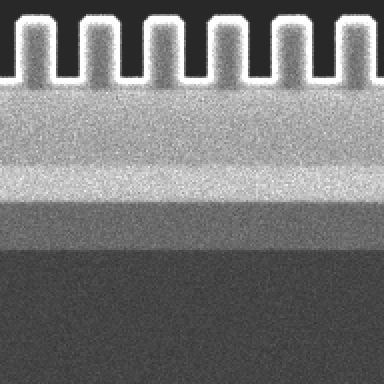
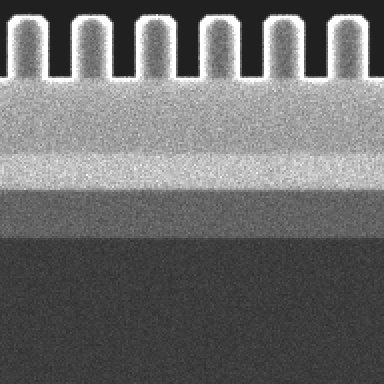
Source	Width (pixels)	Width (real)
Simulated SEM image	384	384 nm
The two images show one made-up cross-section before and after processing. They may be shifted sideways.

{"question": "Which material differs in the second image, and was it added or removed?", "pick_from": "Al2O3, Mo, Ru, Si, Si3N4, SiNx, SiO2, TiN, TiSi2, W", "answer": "SiO2, removed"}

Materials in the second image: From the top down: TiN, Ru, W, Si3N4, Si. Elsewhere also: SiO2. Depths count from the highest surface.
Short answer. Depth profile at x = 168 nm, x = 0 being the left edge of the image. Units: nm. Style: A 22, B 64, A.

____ SiO2 62, Ru 76, W 36, Si3N4 48, Si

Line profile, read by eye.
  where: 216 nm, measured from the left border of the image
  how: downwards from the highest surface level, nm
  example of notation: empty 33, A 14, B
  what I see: TiN 62, Ru 76, W 36, Si3N4 48, Si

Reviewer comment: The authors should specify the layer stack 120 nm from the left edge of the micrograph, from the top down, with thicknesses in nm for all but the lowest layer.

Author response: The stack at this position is empty 62, Ru 76, W 36, Si3N4 48, Si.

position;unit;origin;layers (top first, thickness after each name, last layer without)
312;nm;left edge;empty 62, Ru 76, W 36, Si3N4 48, Si